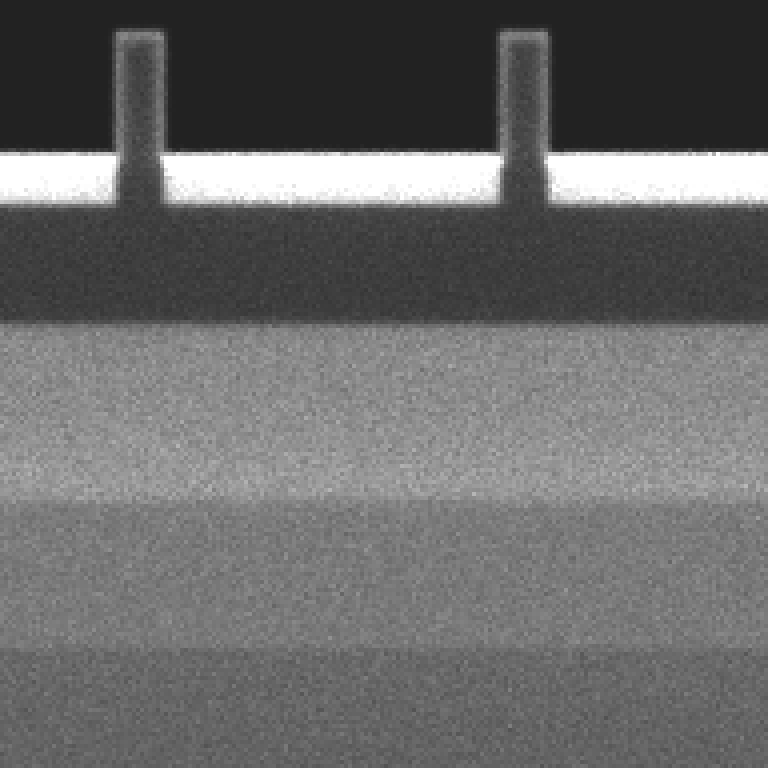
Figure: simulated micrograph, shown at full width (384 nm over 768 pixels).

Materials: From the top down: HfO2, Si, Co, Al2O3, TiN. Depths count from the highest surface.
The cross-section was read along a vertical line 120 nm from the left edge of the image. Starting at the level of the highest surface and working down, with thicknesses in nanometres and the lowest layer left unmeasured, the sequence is empty 62, HfO2 24, Si 60, Co 88, Al2O3 74, TiN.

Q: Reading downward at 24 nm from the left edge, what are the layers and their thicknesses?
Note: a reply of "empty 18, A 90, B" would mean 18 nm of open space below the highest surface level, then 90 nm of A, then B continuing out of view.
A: empty 62, HfO2 24, Si 60, Co 88, Al2O3 74, TiN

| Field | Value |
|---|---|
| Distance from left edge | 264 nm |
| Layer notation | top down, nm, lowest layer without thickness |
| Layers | Si 146, Co 88, Al2O3 74, TiN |